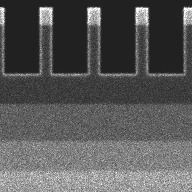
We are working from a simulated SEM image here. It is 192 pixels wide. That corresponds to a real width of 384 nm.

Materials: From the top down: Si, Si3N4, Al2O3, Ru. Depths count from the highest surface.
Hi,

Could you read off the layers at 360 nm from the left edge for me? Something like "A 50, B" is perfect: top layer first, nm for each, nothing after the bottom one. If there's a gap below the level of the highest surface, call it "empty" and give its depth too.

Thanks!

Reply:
empty 132, Si 60, Si3N4 74, Al2O3 60, Ru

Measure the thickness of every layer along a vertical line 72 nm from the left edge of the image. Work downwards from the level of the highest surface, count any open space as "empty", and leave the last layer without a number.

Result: empty 132, Si 60, Si3N4 74, Al2O3 60, Ru